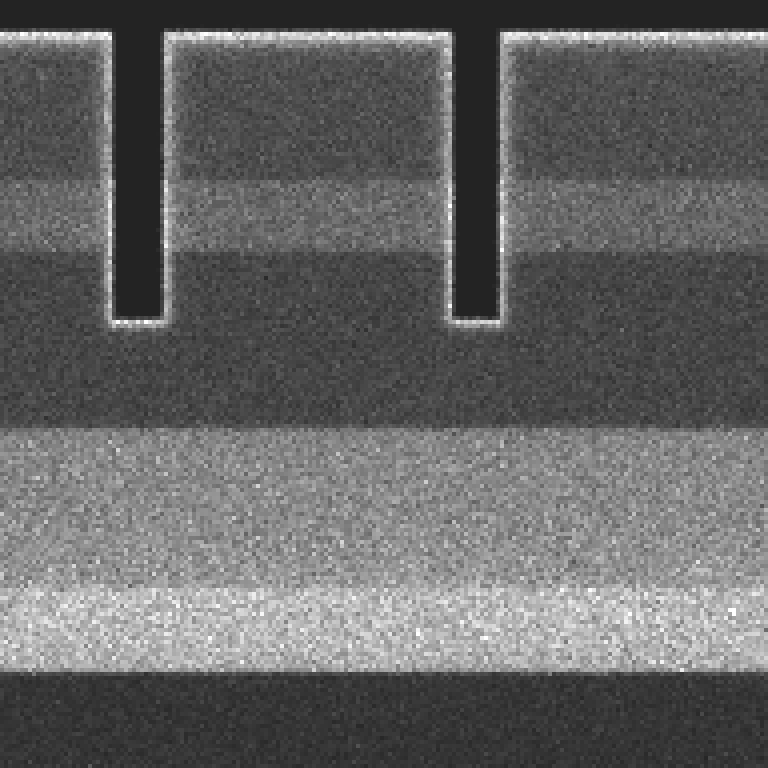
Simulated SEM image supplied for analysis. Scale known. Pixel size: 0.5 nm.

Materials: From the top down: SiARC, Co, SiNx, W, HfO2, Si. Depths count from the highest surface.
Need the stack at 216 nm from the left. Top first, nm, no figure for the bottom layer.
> SiARC 74, Co 36, SiNx 88, W 80, HfO2 42, Si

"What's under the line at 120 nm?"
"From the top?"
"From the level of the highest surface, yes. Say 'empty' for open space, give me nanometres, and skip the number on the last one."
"SiARC 74, Co 36, SiNx 88, W 80, HfO2 42, Si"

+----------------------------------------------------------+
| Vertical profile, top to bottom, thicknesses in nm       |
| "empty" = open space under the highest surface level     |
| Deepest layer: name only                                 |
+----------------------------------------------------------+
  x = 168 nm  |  SiARC 74, Co 36, SiNx 88, W 80, HfO2 42, Si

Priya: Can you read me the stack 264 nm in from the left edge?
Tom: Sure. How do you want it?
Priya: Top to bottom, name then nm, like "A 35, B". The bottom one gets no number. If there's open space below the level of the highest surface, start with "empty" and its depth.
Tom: SiARC 74, Co 36, SiNx 88, W 80, HfO2 42, Si